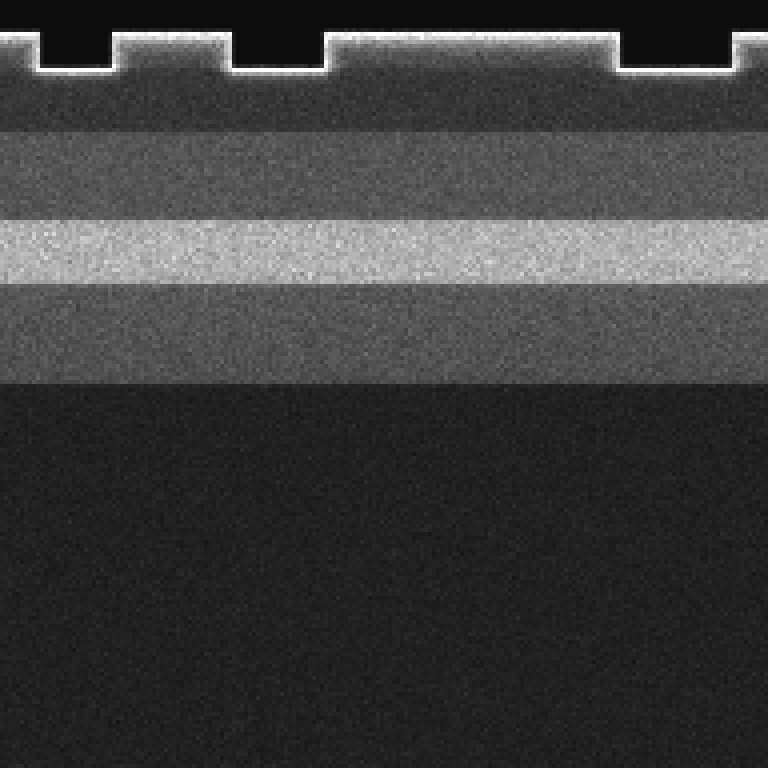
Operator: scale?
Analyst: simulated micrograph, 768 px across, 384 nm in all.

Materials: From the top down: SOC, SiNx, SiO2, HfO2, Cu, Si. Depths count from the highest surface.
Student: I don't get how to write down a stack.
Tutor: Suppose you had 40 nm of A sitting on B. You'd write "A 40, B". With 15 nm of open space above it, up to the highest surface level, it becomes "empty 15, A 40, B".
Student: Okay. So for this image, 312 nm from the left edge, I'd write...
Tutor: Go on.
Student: empty 18, SiNx 32, SiO2 44, HfO2 32, Cu 50, Si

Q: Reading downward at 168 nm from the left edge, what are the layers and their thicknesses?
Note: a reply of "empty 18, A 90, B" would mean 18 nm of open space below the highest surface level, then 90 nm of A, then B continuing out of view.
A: SOC 18, SiNx 32, SiO2 44, HfO2 32, Cu 50, Si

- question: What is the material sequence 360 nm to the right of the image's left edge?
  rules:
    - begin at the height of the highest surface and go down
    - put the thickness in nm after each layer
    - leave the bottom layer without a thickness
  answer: empty 18, SiNx 32, SiO2 44, HfO2 32, Cu 50, Si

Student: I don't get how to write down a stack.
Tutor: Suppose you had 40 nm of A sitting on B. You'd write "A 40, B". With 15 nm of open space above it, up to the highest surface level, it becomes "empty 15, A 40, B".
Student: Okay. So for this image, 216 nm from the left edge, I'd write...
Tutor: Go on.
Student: SOC 18, SiNx 32, SiO2 44, HfO2 32, Cu 50, Si